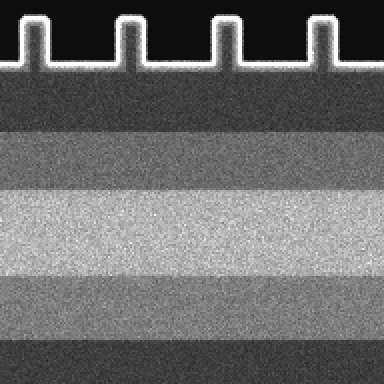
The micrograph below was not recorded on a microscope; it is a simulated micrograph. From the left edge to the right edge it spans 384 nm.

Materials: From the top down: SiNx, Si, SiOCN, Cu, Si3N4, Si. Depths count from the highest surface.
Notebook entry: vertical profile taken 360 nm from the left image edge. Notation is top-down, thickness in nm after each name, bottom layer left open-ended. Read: empty 46, SiNx 10, Si 60, SiOCN 58, Cu 86, Si3N4 64, Si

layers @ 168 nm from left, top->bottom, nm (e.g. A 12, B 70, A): empty 46, SiNx 10, Si 60, SiOCN 58, Cu 86, Si3N4 64, Si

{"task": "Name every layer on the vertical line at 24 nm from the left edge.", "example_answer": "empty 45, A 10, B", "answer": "SiNx 56, Si 60, SiOCN 58, Cu 86, Si3N4 64, Si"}